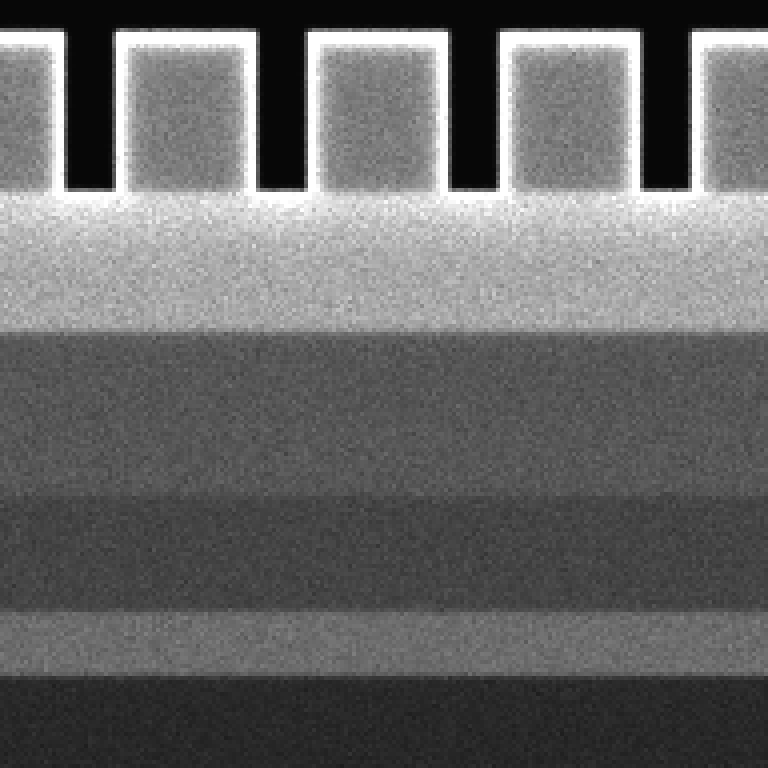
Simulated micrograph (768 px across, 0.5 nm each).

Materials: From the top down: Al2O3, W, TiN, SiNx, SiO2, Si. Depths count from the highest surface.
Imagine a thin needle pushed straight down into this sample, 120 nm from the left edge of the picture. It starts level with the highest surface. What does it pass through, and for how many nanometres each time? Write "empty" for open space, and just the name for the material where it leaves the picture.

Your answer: Al2O3 80, W 70, TiN 82, SiNx 58, SiO2 32, Si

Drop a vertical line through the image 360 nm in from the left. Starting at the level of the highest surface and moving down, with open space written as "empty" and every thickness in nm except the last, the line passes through Al2O3 80, W 70, TiN 82, SiNx 58, SiO2 32, Si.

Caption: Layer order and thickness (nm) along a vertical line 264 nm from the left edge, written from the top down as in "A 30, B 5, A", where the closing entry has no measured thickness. Al2O3 80, W 70, TiN 82, SiNx 58, SiO2 32, Si